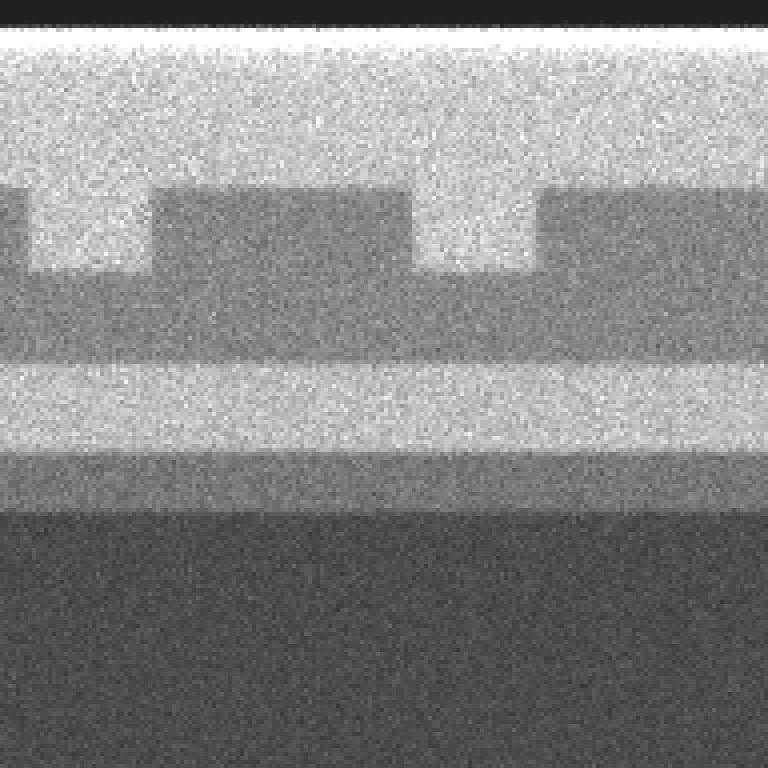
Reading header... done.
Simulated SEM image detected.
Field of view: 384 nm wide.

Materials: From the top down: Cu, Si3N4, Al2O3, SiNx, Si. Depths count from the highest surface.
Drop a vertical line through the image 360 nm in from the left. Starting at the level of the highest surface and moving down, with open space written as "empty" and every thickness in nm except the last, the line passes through Cu 78, Si3N4 88, Al2O3 44, SiNx 30, Si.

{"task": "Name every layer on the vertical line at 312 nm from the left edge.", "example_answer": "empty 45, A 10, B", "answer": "Cu 78, Si3N4 88, Al2O3 44, SiNx 30, Si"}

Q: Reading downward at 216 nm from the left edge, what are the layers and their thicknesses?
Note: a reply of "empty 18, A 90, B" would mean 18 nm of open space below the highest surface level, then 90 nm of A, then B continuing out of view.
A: Cu 120, Si3N4 46, Al2O3 44, SiNx 30, Si